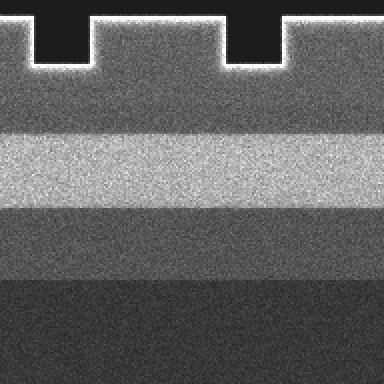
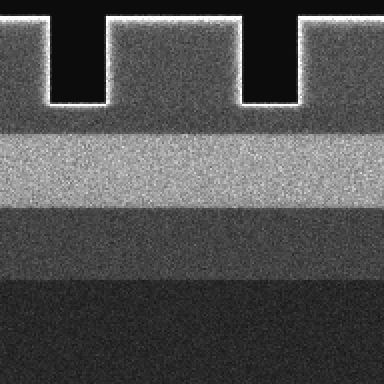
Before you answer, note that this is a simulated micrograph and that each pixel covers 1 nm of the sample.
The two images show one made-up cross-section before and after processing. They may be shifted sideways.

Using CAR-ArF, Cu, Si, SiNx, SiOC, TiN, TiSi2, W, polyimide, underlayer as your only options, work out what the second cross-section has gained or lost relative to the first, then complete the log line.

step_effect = removed underlayer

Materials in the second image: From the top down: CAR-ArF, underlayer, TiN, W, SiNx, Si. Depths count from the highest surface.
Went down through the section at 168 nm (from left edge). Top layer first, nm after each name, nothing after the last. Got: CAR-ArF 48, underlayer 40, TiN 30, W 74, SiNx 72, Si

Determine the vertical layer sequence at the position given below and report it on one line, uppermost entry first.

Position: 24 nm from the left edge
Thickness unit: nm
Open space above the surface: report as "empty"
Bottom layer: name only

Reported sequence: CAR-ArF 48, underlayer 40, TiN 30, W 74, SiNx 72, Si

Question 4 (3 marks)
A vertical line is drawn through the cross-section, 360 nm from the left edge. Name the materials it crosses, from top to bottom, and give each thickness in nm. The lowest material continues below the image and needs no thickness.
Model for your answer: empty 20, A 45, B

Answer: CAR-ArF 48, underlayer 40, TiN 30, W 74, SiNx 72, Si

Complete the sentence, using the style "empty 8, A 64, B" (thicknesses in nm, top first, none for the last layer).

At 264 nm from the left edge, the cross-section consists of empty 88, TiN 30, W 74, SiNx 72, Si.